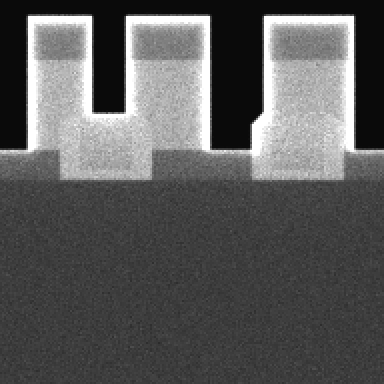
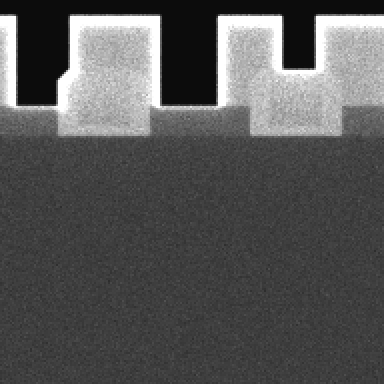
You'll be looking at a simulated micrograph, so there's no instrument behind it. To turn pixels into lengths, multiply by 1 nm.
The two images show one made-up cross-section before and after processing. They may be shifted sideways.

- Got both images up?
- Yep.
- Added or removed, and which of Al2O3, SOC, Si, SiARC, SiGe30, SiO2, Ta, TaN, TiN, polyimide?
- removed, SOC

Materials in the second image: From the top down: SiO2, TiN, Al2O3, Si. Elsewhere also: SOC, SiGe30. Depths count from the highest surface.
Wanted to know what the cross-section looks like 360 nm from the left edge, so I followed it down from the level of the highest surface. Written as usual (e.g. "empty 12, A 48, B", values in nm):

SiO2 90, SiGe30 30, Si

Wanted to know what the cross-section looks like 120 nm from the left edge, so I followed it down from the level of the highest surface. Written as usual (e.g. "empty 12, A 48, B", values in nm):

SiO2 54, TiN 56, Al2O3 10, Si